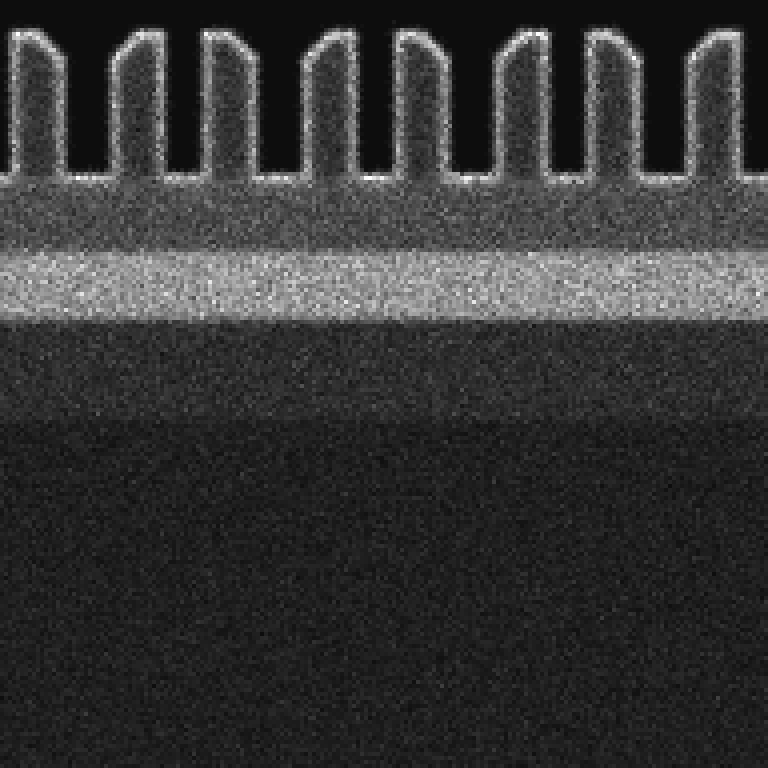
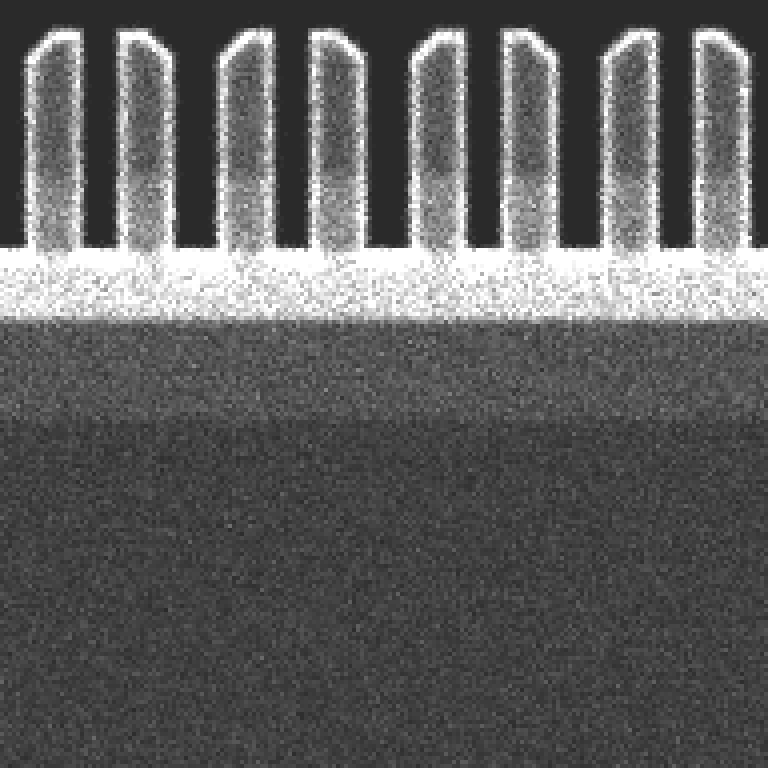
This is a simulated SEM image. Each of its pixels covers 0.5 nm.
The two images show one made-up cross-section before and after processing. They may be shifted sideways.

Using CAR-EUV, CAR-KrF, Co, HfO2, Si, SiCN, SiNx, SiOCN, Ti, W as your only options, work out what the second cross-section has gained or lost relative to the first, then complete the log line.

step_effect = removed Co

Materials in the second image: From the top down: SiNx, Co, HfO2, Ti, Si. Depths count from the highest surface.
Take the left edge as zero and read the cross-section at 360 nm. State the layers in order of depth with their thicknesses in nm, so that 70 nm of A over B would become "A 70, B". SiNx 72, Co 38, HfO2 34, Ti 50, Si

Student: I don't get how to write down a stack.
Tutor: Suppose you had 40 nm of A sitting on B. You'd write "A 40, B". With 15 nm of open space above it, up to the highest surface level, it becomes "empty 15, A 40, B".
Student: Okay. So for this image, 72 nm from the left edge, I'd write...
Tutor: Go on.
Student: SiNx 72, Co 38, HfO2 34, Ti 50, Si